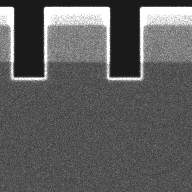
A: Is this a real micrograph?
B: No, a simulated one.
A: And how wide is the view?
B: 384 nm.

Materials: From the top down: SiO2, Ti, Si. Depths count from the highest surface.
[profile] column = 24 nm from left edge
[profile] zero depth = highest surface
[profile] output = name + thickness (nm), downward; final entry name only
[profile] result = SiO2 34, Ti 74, Si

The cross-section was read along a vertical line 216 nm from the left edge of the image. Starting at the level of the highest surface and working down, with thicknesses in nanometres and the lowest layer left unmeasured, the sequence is SiO2 34, Ti 74, Si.